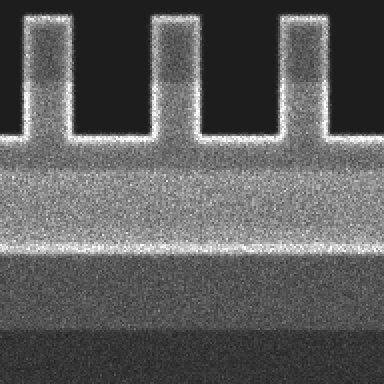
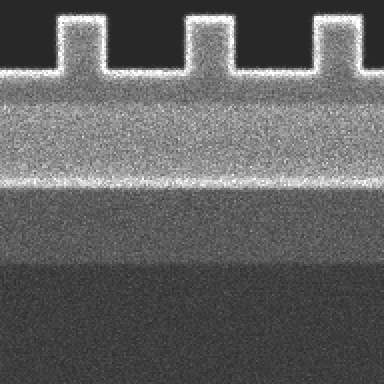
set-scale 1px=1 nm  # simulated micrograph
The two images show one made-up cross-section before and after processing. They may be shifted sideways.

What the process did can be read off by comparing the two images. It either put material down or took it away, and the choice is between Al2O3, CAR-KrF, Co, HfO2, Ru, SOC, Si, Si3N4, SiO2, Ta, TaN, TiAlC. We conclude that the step removed SOC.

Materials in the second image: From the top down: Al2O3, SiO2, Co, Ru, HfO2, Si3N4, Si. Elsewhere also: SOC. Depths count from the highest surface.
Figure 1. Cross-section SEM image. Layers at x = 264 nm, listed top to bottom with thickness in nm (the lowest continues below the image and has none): empty 54, SiO2 34, Co 58, Ru 16, HfO2 10, Si3N4 76, Si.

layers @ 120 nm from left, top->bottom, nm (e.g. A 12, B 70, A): empty 54, SiO2 34, Co 58, Ru 16, HfO2 10, Si3N4 76, Si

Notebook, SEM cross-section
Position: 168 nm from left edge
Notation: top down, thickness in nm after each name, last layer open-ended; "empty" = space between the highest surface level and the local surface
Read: empty 54, SiO2 34, Co 58, Ru 16, HfO2 10, Si3N4 76, Si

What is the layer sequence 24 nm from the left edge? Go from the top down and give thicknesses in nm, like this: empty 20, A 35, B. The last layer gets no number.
empty 54, SiO2 34, Co 58, Ru 16, HfO2 10, Si3N4 76, Si